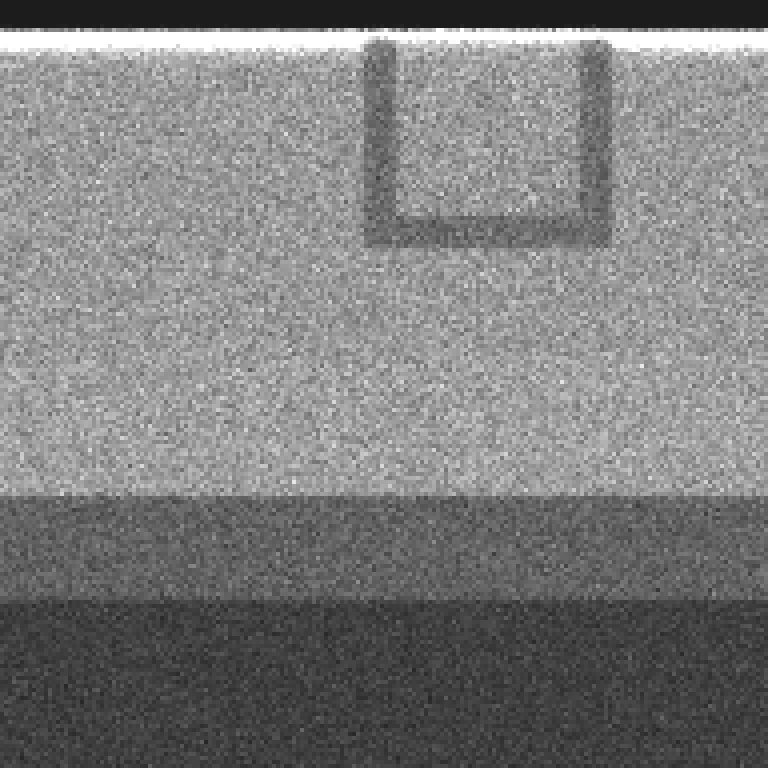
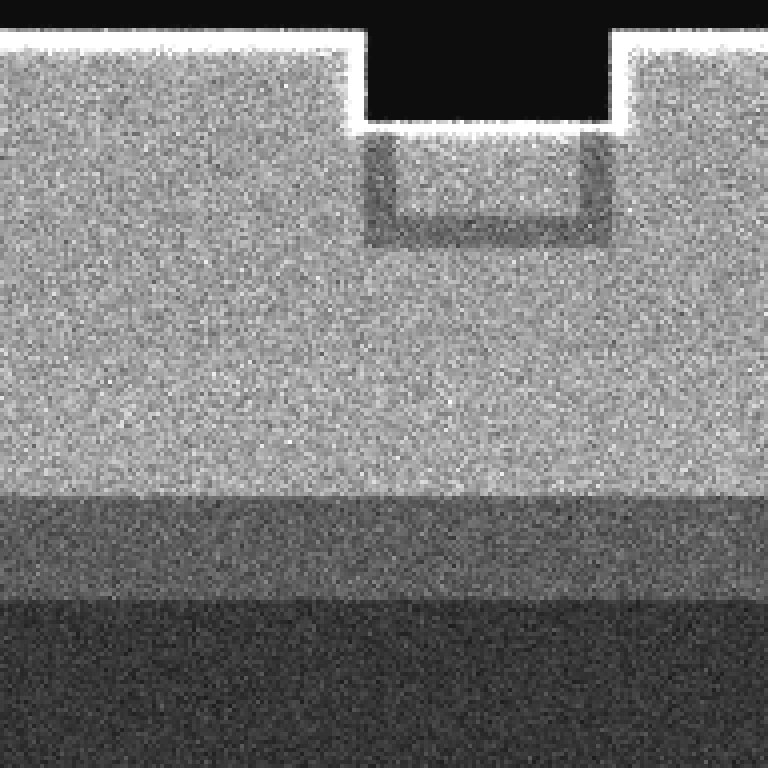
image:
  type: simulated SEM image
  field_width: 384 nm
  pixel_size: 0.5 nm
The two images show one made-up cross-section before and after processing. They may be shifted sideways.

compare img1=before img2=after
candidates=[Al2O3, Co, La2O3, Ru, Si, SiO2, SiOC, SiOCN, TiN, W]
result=removed:Co and TiN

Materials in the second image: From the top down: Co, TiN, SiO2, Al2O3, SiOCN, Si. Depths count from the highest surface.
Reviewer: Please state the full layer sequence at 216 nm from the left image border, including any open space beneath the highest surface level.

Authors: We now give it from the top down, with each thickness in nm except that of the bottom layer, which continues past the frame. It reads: empty 46, Co 46, TiN 16, SiO2 52, Al2O3 72, SiOCN 52, Si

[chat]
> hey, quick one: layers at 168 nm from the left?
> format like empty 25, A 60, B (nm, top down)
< SiO2 160, Al2O3 72, SiOCN 52, Si